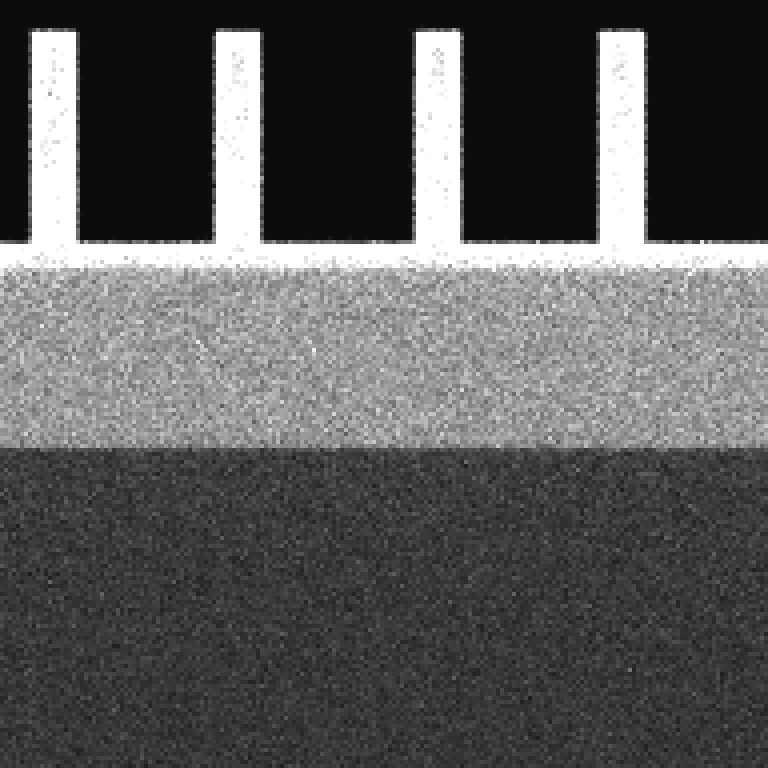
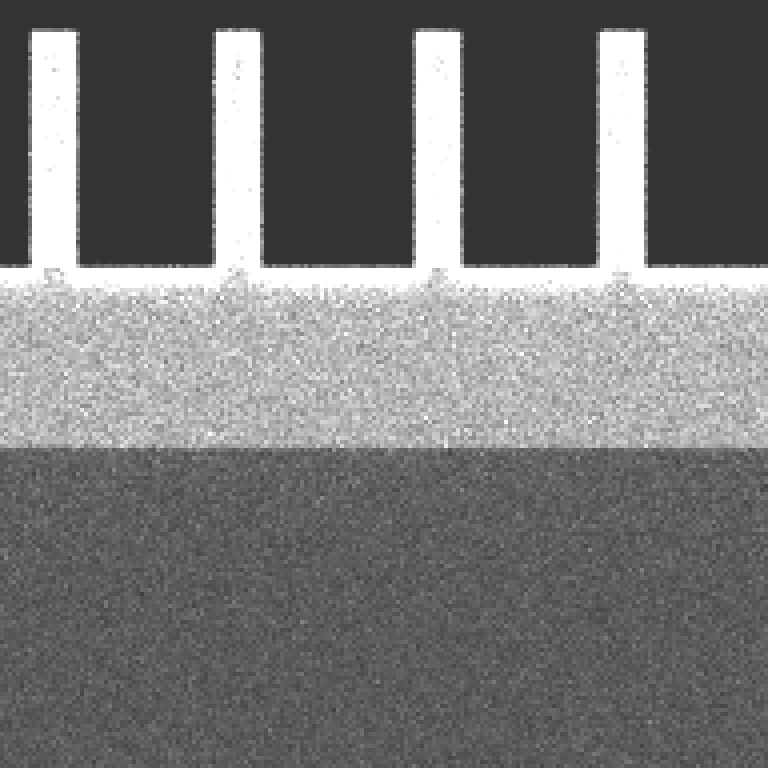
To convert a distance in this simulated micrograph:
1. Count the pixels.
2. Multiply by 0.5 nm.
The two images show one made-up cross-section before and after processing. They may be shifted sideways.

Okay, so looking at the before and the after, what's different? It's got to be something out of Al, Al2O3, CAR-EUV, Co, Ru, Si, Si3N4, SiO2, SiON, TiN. Co, removed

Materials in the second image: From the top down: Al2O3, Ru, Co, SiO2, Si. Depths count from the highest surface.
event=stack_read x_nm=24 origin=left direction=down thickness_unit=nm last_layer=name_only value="Al2O3 24, Ru 82, Co 12, SiO2 90, Si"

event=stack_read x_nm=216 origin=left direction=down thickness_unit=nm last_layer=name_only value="Al2O3 24, Ru 82, Co 12, SiO2 90, Si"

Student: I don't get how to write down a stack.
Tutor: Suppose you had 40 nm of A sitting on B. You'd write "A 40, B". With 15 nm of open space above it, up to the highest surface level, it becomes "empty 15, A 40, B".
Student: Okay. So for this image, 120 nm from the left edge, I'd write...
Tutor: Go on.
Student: Al2O3 24, Ru 82, Co 12, SiO2 90, Si